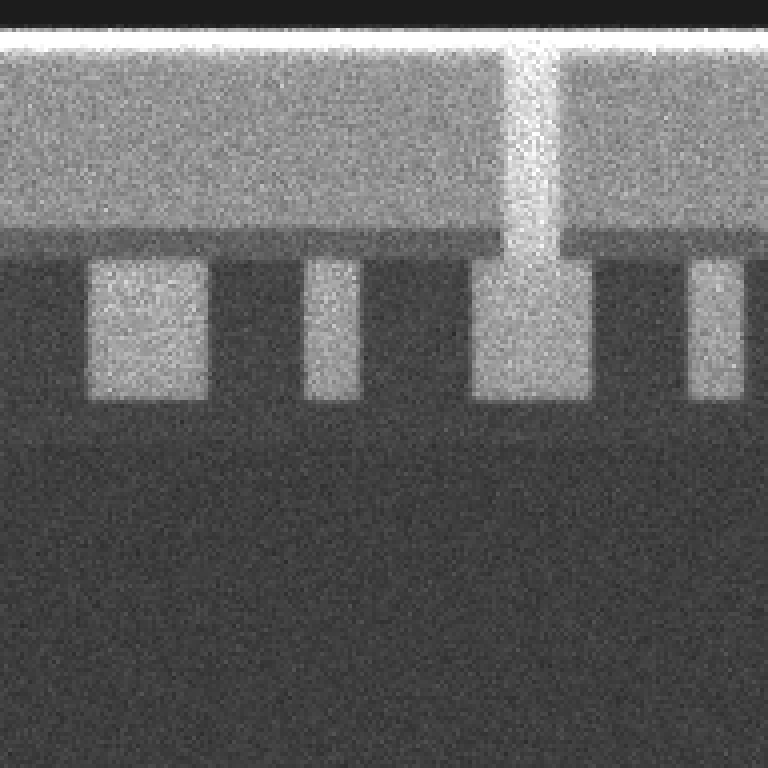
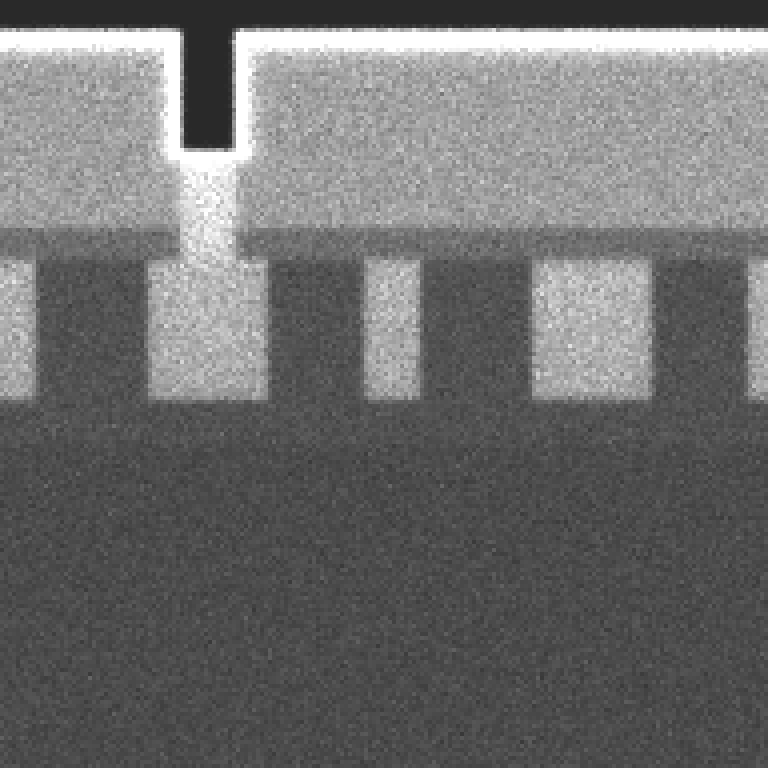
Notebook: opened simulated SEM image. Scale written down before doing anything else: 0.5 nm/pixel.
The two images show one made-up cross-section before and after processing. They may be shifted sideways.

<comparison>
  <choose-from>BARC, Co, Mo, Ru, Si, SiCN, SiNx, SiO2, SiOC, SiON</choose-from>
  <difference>Ru removed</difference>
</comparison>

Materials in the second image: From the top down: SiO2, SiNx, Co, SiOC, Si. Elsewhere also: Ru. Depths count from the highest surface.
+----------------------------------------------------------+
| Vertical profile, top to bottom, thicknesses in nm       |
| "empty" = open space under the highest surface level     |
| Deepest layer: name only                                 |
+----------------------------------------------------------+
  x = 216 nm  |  SiO2 98, SiNx 16, SiOC 92, Si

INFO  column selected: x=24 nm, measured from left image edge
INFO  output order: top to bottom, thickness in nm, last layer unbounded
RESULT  SiO2 98, SiNx 16, SiOC 92, Si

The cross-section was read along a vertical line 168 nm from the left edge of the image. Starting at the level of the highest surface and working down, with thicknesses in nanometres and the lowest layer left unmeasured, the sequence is SiO2 98, SiNx 16, SiOC 92, Si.